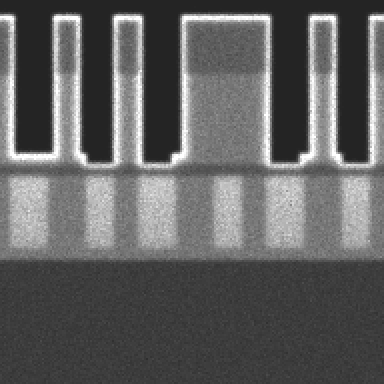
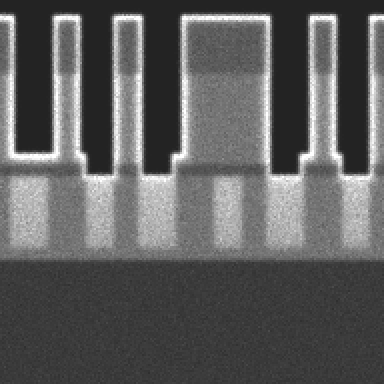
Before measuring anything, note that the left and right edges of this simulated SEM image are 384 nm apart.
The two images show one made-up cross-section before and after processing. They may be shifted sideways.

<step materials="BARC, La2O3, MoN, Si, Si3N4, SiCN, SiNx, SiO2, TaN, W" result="removed SiNx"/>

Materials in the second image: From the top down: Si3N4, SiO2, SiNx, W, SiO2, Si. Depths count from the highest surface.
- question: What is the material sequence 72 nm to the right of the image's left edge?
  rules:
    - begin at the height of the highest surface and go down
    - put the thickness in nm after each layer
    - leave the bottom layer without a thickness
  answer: Si3N4 58, SiO2 90, SiNx 12, SiO2 84, Si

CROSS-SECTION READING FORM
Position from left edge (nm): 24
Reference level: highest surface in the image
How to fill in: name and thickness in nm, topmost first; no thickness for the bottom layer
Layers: empty 138, SiO2 10, SiNx 12, W 72, SiO2 12, Si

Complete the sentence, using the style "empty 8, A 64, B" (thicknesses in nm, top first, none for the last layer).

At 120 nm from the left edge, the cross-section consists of Si3N4 58, SiO2 90, SiNx 12, SiO2 84, Si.